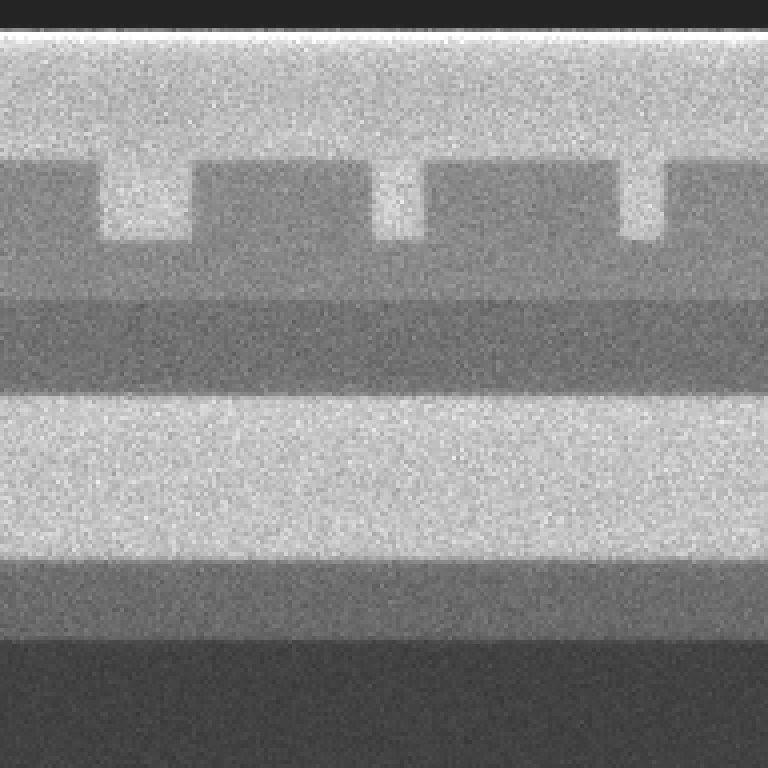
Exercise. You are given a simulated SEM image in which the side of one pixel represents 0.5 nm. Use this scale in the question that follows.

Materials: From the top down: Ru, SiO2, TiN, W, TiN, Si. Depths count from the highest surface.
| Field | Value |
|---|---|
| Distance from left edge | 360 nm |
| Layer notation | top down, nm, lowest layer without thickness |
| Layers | Ru 64, SiO2 70, TiN 48, W 82, TiN 40, Si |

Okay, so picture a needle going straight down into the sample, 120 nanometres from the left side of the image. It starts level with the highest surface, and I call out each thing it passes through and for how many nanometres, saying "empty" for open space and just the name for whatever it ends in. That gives Ru 64, SiO2 70, TiN 48, W 82, TiN 40, Si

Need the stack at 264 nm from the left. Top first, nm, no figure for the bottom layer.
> Ru 64, SiO2 70, TiN 48, W 82, TiN 40, Si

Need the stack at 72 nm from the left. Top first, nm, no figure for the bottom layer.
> Ru 104, SiO2 30, TiN 48, W 82, TiN 40, Si